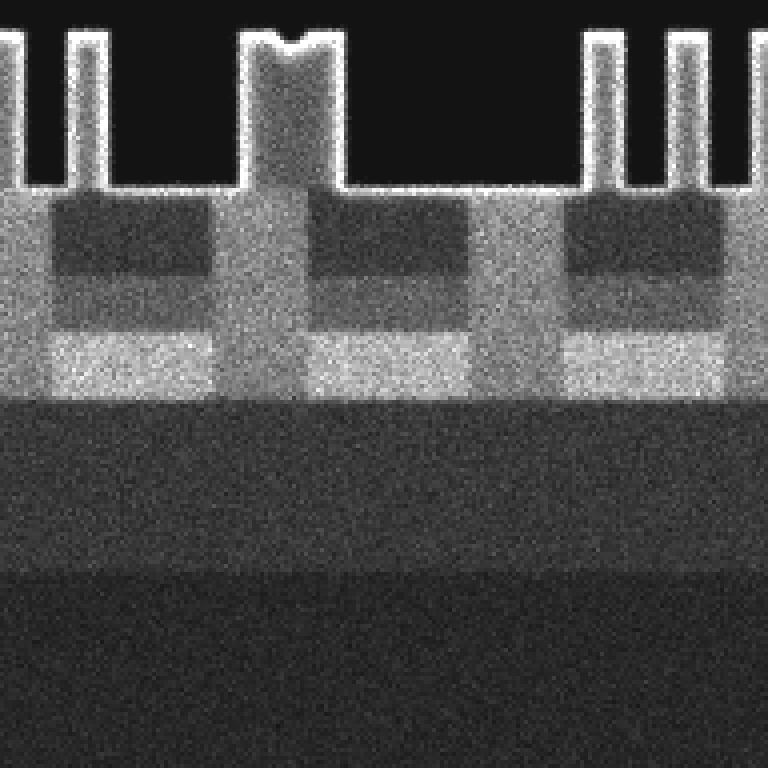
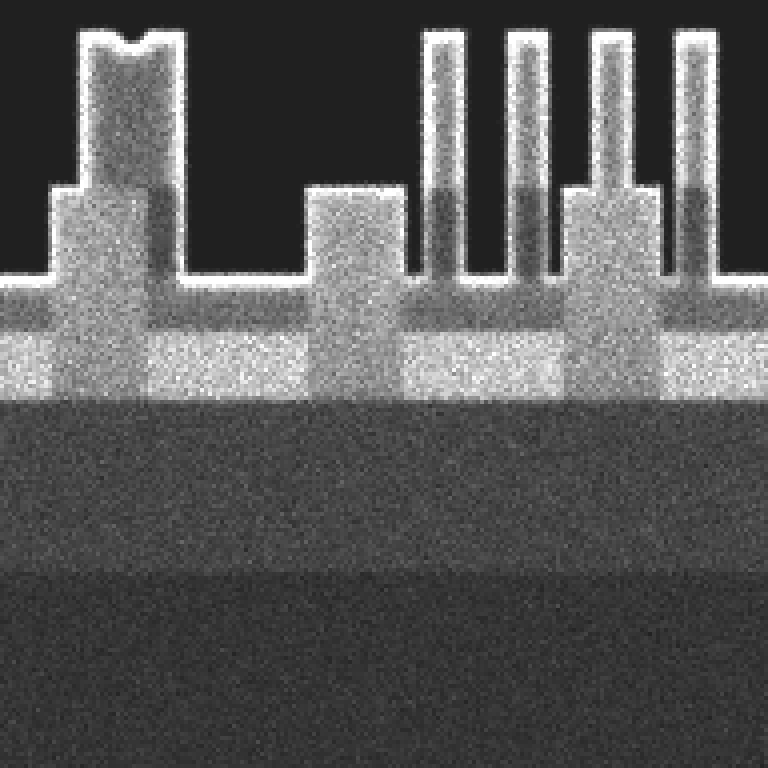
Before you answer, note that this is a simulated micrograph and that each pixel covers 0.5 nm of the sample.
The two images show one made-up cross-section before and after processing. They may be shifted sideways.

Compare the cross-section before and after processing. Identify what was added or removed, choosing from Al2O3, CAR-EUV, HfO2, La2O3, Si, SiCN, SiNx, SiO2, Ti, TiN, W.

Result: SiNx removed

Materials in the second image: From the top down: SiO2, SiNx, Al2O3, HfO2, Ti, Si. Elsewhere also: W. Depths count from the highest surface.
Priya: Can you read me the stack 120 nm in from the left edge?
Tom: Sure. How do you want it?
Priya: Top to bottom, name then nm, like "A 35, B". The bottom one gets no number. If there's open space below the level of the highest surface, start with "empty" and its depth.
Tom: empty 122, Al2O3 28, HfO2 34, Ti 86, Si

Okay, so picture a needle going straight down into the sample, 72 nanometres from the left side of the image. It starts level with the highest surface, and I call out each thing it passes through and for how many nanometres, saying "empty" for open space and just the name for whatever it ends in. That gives empty 2, SiO2 76, W 106, Ti 86, Si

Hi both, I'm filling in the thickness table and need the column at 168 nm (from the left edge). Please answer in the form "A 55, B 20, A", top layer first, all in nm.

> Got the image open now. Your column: empty 78, W 106, Ti 86, Si